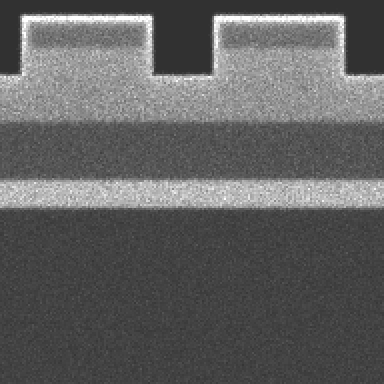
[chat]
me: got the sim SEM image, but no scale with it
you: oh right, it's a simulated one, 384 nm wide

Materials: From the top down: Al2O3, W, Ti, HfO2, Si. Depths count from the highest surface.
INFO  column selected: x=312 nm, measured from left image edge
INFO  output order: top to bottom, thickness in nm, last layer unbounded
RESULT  Al2O3 32, W 74, Ti 58, HfO2 28, Si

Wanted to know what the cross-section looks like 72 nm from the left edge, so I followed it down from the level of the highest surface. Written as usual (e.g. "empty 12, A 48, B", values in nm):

Al2O3 32, W 74, Ti 58, HfO2 28, Si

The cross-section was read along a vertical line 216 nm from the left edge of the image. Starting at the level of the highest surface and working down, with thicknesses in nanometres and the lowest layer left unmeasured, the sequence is Al2O3 32, W 74, Ti 58, HfO2 28, Si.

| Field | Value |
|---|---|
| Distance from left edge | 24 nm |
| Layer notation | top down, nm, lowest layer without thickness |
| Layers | Al2O3 32, W 74, Ti 58, HfO2 28, Si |